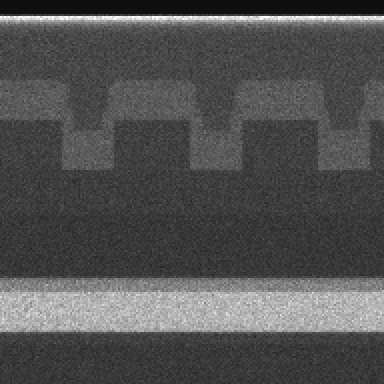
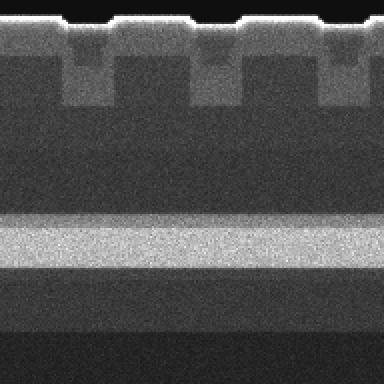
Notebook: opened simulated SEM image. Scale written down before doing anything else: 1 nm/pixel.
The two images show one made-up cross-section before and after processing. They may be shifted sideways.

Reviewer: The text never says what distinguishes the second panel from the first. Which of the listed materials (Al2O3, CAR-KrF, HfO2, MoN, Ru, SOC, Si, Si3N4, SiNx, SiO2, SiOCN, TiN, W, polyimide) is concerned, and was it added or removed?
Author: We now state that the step removed SOC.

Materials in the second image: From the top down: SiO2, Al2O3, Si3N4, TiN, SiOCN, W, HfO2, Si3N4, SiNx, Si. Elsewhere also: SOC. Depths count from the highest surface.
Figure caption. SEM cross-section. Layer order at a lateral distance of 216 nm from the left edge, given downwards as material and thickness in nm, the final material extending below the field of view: empty 8, SOC 42, SiO2 10, Al2O3 30, TiN 44, SiOCN 64, W 14, HfO2 40, Si3N4 12, SiNx 52, Si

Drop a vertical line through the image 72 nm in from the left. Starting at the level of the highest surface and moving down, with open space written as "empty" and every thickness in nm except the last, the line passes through empty 8, SOC 24, SiO2 28, Al2O3 30, TiN 44, SiOCN 64, W 14, HfO2 40, Si3N4 12, SiNx 52, Si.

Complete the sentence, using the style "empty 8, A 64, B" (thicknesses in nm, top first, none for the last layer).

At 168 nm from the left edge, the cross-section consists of SiO2 10, Al2O3 30, Si3N4 50, TiN 44, SiOCN 64, W 14, HfO2 40, Si3N4 12, SiNx 52, Si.